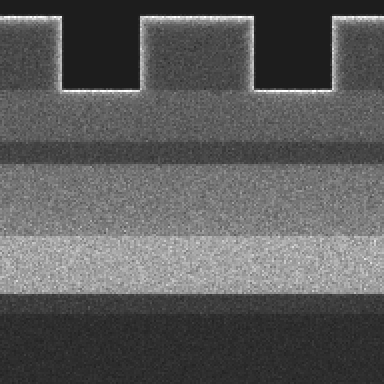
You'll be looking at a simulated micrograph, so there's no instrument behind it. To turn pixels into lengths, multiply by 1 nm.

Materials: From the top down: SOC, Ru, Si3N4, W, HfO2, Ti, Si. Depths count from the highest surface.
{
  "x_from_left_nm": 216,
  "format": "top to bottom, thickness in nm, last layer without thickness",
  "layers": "SOC 74, Ru 52, Si3N4 22, W 72, HfO2 58, Ti 20, Si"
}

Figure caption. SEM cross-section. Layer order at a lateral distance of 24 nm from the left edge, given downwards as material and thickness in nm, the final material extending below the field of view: SOC 74, Ru 52, Si3N4 22, W 72, HfO2 58, Ti 20, Si